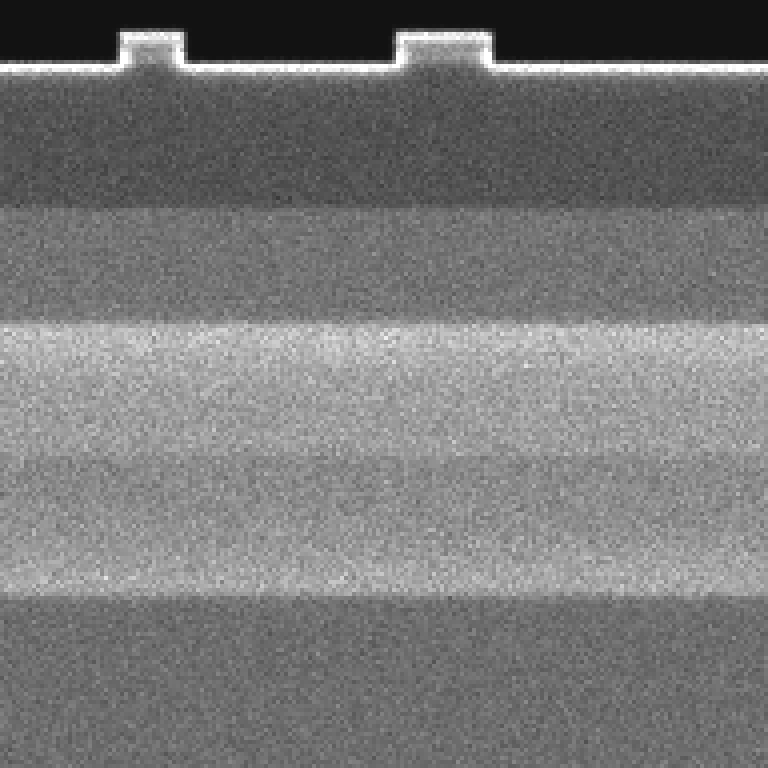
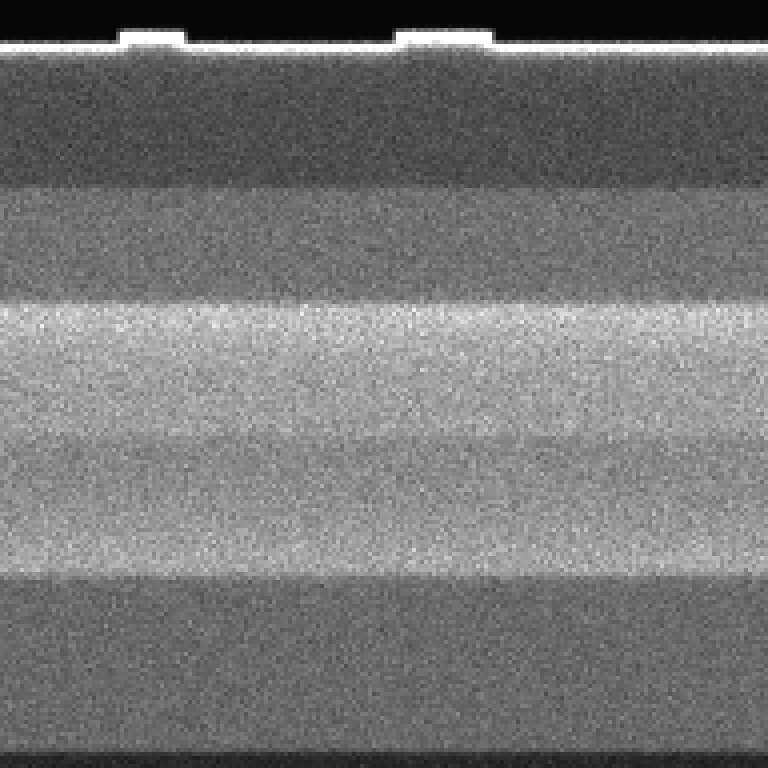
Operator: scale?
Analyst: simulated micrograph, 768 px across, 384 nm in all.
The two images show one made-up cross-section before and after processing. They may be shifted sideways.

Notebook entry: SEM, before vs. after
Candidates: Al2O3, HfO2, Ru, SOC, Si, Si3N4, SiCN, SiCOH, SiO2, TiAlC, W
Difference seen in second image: SOC removed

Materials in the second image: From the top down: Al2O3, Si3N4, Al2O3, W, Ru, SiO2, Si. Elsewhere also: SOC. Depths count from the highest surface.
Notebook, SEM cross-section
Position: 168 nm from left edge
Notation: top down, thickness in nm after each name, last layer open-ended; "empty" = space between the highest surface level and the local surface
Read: empty 6, Si3N4 72, Al2O3 58, W 66, Ru 70, SiO2 88, Si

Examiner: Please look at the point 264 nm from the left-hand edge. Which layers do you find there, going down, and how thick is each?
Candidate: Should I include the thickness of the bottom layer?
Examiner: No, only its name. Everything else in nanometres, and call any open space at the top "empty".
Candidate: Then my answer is empty 6, Si3N4 72, Al2O3 58, W 66, Ru 70, SiO2 88, Si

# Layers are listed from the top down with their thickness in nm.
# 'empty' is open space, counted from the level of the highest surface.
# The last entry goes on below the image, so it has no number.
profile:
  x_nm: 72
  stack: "Al2O3 6, Si3N4 72, Al2O3 58, W 66, Ru 70, SiO2 88, Si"